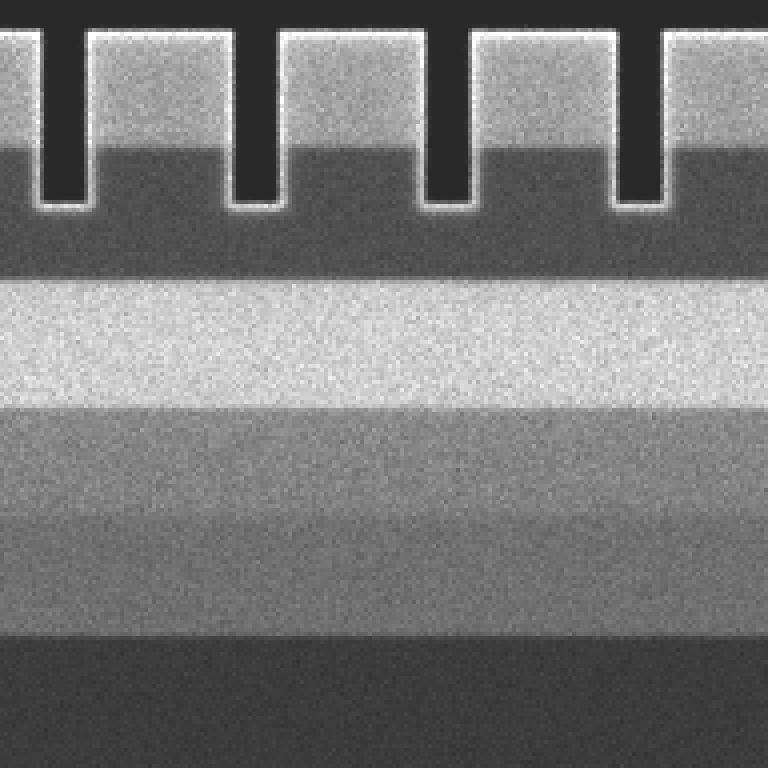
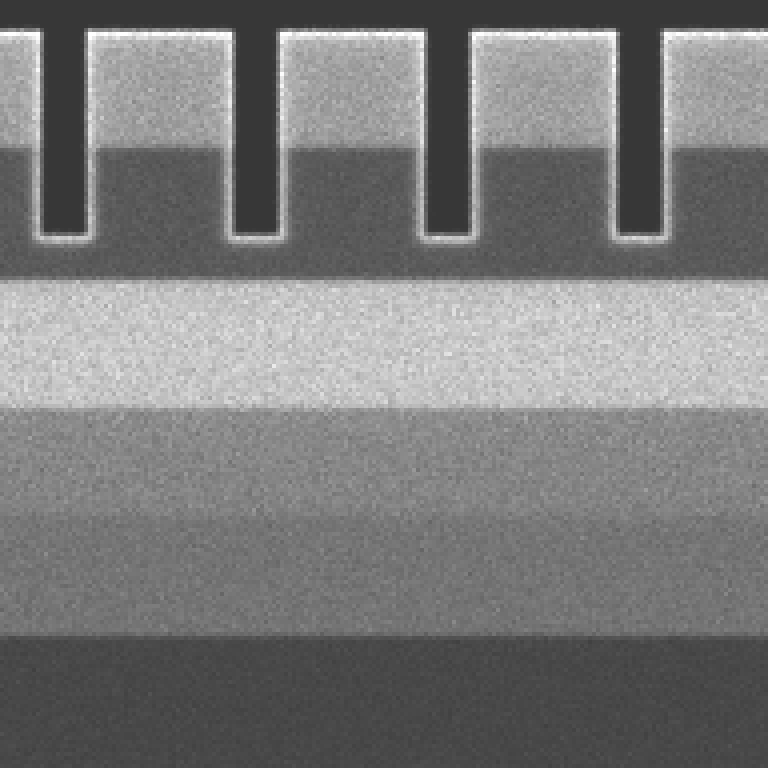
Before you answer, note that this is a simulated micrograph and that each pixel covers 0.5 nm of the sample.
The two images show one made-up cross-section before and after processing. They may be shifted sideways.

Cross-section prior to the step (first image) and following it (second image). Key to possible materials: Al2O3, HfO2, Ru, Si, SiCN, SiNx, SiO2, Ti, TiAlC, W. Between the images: SiNx was removed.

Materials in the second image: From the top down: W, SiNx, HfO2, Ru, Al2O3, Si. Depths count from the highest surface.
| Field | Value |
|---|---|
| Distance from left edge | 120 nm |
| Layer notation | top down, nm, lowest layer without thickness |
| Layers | empty 102, SiNx 22, HfO2 64, Ru 54, Al2O3 60, Si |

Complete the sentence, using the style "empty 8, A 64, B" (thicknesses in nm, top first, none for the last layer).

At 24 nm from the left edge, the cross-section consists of empty 102, SiNx 22, HfO2 64, Ru 54, Al2O3 60, Si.